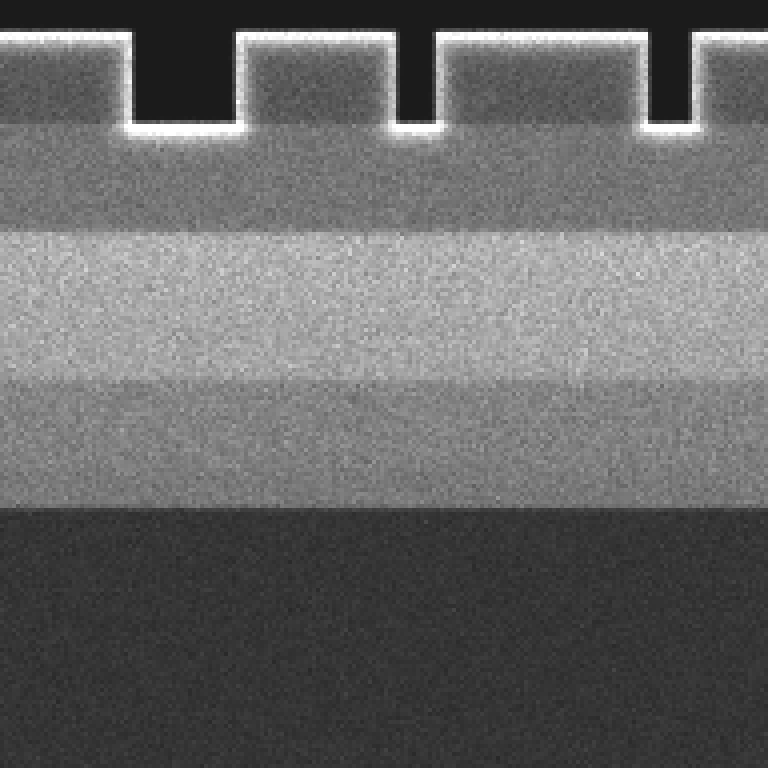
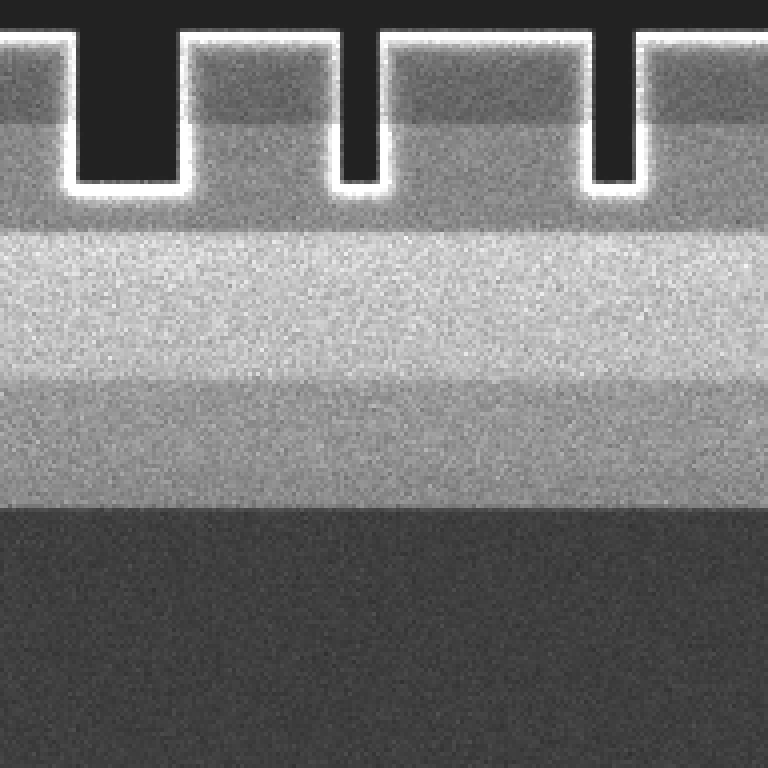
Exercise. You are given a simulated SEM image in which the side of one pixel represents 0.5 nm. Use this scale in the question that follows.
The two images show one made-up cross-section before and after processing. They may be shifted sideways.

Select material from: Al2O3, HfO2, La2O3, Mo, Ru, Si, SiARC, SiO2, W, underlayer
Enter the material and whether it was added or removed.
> SiO2 / removed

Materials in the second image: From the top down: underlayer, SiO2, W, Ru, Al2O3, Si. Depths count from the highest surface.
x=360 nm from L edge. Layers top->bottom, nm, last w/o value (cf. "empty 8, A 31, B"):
underlayer 46, SiO2 54, W 74, Ru 46, Al2O3 18, Si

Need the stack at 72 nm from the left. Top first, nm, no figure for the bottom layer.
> empty 76, SiO2 24, W 74, Ru 46, Al2O3 18, Si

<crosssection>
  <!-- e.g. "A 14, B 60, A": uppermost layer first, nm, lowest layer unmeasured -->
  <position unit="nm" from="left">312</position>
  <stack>empty 76, SiO2 24, W 74, Ru 46, Al2O3 18, Si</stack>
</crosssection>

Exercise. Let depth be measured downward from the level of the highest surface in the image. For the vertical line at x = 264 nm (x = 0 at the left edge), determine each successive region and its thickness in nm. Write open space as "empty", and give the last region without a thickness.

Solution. underlayer 46, SiO2 54, W 74, Ru 46, Al2O3 18, Si